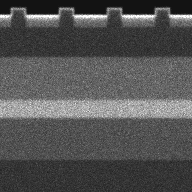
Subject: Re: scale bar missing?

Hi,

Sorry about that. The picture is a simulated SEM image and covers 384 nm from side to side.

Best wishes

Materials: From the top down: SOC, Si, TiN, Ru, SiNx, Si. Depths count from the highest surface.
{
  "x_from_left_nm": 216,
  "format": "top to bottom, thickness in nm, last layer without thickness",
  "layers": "Si 98, TiN 86, Ru 36, SiNx 84, Si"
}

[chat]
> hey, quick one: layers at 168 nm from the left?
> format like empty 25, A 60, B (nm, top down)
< empty 14, SOC 24, Si 60, TiN 86, Ru 36, SiNx 84, Si